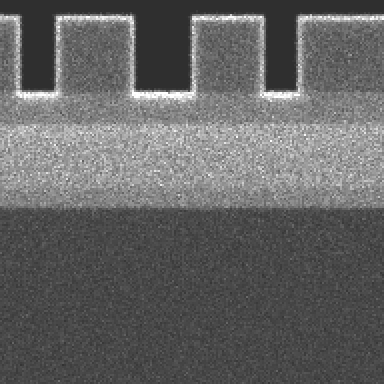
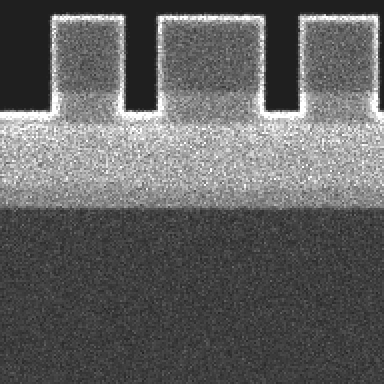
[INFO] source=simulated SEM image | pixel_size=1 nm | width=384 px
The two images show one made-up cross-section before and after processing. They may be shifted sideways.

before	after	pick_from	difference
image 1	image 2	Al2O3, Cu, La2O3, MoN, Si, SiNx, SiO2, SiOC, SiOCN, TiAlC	SiO2 removed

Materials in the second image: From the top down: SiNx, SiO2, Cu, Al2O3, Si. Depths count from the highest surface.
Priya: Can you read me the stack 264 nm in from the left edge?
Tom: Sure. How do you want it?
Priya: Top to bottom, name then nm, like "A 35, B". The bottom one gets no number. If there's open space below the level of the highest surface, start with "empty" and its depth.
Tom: empty 96, SiO2 12, Cu 64, Al2O3 20, Si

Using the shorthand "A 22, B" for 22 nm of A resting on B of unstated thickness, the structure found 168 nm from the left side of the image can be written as SiNx 76, SiO2 32, Cu 64, Al2O3 20, Si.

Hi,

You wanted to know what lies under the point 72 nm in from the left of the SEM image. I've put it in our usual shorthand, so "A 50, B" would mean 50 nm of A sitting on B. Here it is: SiNx 76, SiO2 32, Cu 64, Al2O3 20, Si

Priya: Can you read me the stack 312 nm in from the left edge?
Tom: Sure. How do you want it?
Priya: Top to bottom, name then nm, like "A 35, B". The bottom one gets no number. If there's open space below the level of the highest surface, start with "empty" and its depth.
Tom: SiNx 76, SiO2 32, Cu 64, Al2O3 20, Si